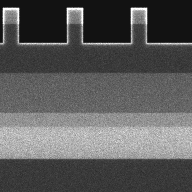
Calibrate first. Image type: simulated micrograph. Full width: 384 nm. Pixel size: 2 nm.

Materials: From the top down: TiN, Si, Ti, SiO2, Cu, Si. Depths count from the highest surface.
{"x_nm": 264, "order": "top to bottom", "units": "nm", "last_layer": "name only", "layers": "TiN 32, Si 98, Ti 80, SiO2 28, Cu 64, Si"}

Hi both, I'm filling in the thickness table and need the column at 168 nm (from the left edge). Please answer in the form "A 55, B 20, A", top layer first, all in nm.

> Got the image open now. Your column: empty 70, Si 60, Ti 80, SiO2 28, Cu 64, Si